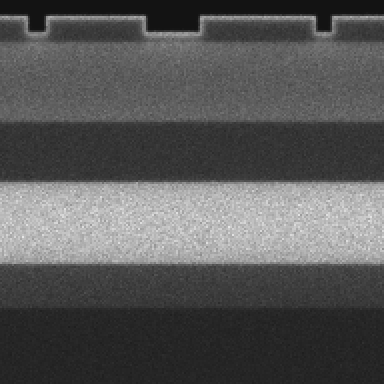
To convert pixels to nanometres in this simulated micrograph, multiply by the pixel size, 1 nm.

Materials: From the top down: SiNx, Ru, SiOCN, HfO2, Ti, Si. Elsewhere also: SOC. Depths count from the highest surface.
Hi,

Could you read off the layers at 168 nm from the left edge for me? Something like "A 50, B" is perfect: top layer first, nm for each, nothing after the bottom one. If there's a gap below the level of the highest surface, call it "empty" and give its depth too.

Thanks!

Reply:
empty 16, SOC 10, Ru 80, SiOCN 60, HfO2 82, Ti 44, Si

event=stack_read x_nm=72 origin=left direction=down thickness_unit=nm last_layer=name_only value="SiNx 26, Ru 80, SiOCN 60, HfO2 82, Ti 44, Si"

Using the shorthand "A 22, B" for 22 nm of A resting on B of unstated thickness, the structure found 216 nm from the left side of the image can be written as SiNx 26, Ru 80, SiOCN 60, HfO2 82, Ti 44, Si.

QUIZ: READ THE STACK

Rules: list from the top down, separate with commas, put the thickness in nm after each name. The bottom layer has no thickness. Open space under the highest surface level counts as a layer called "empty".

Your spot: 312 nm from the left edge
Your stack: SiNx 26, Ru 80, SiOCN 60, HfO2 82, Ti 44, Si